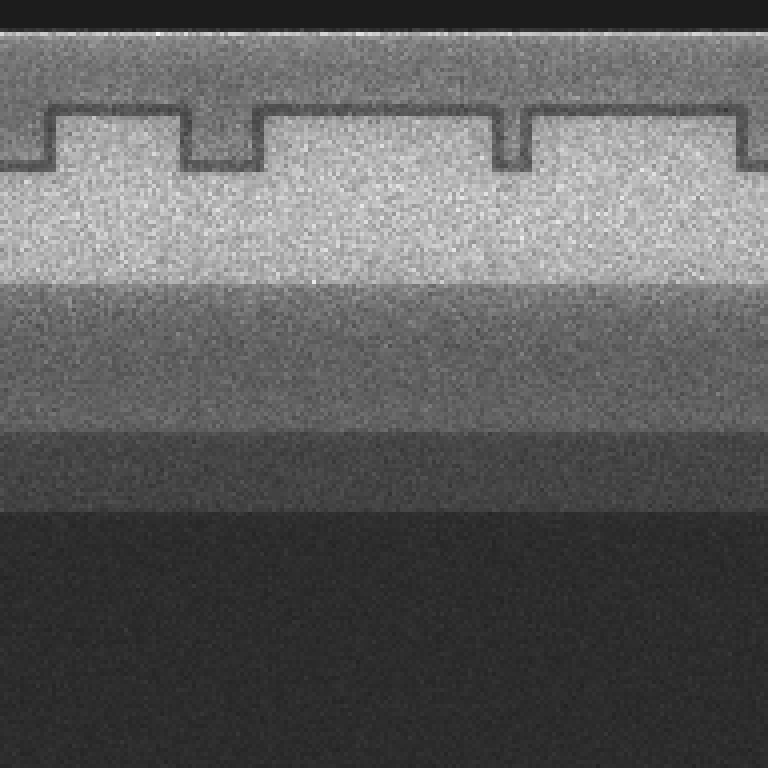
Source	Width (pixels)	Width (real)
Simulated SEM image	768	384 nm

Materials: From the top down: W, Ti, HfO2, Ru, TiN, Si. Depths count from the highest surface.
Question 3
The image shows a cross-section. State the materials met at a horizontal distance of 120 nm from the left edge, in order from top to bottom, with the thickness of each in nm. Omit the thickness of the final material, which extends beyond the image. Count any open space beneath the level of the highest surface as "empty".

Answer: W 64, Ti 6, HfO2 56, Ru 74, TiN 40, Si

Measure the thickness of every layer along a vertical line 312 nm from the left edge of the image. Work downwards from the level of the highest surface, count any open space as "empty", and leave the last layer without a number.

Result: W 36, Ti 6, HfO2 84, Ru 74, TiN 40, Si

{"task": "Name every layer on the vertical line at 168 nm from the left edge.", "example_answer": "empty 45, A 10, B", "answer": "W 36, Ti 6, HfO2 84, Ru 74, TiN 40, Si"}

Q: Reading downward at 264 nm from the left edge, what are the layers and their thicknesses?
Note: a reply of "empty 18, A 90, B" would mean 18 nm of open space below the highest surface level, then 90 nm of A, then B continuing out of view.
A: W 36, Ti 34, HfO2 56, Ru 74, TiN 40, Si